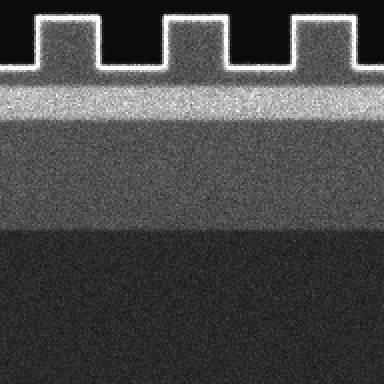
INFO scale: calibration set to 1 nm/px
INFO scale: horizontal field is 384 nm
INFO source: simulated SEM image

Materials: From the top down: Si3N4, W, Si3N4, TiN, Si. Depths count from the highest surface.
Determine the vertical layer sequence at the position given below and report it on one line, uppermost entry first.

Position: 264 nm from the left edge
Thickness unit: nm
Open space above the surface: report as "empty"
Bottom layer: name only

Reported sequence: empty 50, Si3N4 20, W 34, Si3N4 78, TiN 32, Si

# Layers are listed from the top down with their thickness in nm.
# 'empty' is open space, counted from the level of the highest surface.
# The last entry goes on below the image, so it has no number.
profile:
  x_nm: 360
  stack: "empty 50, Si3N4 20, W 34, Si3N4 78, TiN 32, Si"